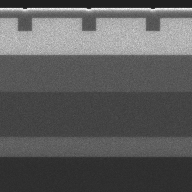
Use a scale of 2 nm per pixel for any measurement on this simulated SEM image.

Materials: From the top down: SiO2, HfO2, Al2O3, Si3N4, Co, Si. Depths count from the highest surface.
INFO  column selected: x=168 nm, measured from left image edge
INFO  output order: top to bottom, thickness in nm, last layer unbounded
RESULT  SiO2 46, HfO2 48, Al2O3 74, Si3N4 90, Co 40, Si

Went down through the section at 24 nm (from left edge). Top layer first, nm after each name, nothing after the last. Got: SiO2 20, HfO2 74, Al2O3 74, Si3N4 90, Co 40, Si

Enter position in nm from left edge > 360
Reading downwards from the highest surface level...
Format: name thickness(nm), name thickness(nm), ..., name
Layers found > SiO2 20, HfO2 74, Al2O3 74, Si3N4 90, Co 40, Si